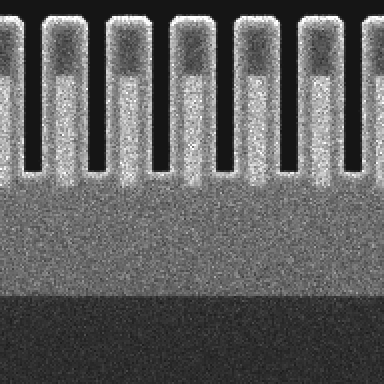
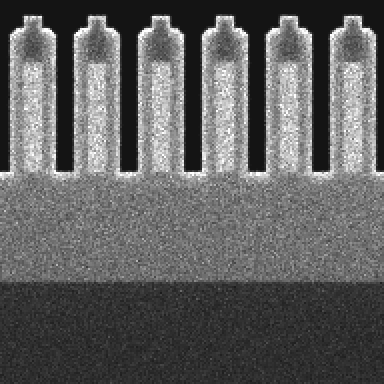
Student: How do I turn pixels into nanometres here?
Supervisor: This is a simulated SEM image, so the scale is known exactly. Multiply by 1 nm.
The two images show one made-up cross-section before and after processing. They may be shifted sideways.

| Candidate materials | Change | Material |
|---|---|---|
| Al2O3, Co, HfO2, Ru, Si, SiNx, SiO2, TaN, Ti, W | removed | SiO2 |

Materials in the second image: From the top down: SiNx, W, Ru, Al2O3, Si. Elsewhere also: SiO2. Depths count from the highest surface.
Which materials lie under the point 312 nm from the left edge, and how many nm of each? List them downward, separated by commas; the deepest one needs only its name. empty 156, Al2O3 110, Si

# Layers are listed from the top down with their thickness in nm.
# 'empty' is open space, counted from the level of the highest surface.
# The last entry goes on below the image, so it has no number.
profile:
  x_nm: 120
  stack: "empty 156, Al2O3 110, Si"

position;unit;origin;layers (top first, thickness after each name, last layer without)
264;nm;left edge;empty 156, Al2O3 110, Si